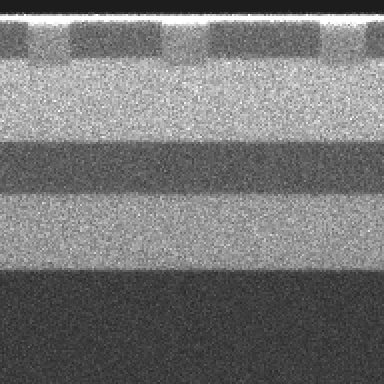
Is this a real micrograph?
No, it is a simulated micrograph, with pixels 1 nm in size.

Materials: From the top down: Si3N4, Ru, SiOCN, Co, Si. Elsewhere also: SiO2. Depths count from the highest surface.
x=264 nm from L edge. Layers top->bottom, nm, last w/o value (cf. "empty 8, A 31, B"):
Si3N4 42, Ru 84, SiOCN 52, Co 76, Si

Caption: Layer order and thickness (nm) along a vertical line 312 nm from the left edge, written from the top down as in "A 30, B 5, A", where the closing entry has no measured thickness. Si3N4 42, Ru 84, SiOCN 52, Co 76, Si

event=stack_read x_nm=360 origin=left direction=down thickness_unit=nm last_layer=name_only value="SiO2 50, Ru 76, SiOCN 52, Co 76, Si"